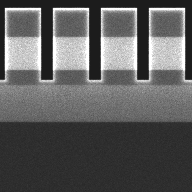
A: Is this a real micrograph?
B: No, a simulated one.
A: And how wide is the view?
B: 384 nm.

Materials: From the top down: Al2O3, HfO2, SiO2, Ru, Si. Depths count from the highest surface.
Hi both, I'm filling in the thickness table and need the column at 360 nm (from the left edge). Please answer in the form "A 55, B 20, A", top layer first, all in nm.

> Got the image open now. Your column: Al2O3 58, HfO2 66, SiO2 30, Ru 74, Si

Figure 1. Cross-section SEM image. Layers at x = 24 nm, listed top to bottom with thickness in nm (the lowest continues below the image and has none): Al2O3 58, HfO2 66, SiO2 30, Ru 74, Si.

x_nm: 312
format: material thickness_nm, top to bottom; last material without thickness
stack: Al2O3 58, HfO2 66, SiO2 30, Ru 74, Si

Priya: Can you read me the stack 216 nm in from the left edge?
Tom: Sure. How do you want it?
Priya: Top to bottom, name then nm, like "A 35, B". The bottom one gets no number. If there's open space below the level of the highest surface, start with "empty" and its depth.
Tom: Al2O3 58, HfO2 66, SiO2 30, Ru 74, Si